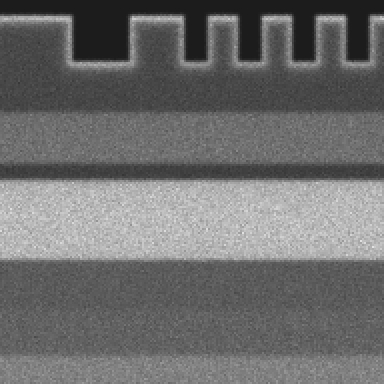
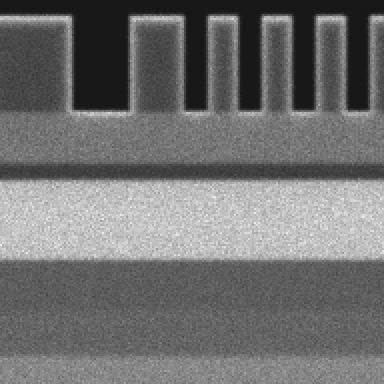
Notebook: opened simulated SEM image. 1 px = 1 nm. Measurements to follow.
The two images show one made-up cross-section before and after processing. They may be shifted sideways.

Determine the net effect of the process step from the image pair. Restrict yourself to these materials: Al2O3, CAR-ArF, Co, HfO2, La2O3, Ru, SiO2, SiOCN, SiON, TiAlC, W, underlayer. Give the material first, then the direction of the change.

underlayer: removed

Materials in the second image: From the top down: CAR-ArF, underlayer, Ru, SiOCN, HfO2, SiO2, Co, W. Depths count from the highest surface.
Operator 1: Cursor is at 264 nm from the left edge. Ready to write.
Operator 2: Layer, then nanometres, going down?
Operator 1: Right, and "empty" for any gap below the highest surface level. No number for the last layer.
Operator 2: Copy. CAR-ArF 46, underlayer 50, Ru 52, SiOCN 16, HfO2 80, SiO2 50, Co 46, W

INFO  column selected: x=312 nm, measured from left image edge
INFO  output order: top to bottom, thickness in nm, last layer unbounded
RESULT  empty 96, Ru 52, SiOCN 16, HfO2 80, SiO2 50, Co 46, W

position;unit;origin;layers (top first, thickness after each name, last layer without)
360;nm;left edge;empty 96, Ru 52, SiOCN 16, HfO2 80, SiO2 50, Co 46, W